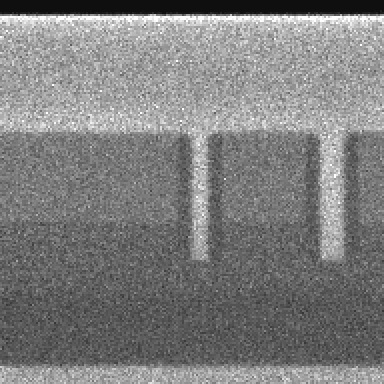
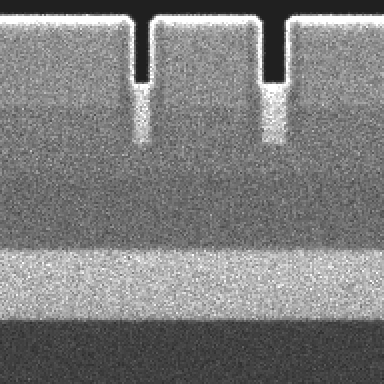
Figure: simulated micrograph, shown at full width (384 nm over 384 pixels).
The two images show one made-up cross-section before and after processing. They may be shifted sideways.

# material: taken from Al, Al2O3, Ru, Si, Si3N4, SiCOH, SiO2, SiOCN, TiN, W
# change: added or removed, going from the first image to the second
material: Ru
change: removed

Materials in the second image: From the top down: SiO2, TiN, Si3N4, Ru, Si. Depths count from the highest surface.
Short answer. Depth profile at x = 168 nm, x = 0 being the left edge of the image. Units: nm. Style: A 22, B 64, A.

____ SiO2 90, TiN 70, Si3N4 74, Ru 70, Si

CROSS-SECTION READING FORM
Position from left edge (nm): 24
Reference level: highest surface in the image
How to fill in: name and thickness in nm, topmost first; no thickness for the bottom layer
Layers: SiO2 90, TiN 70, Si3N4 74, Ru 70, Si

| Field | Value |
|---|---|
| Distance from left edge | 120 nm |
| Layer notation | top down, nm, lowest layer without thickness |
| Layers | Si3N4 128, TiN 32, Si3N4 74, Ru 70, Si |